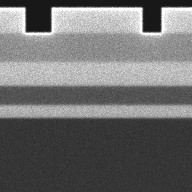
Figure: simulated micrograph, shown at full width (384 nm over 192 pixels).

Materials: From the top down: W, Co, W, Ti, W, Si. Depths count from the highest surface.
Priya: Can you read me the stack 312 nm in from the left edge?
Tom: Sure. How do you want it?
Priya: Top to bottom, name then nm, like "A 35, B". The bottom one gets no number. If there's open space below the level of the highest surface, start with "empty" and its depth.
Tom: empty 50, Co 58, W 48, Ti 38, W 26, Si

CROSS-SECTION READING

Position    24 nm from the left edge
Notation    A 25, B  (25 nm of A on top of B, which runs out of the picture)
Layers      W 50, Co 58, W 48, Ti 38, W 26, Si